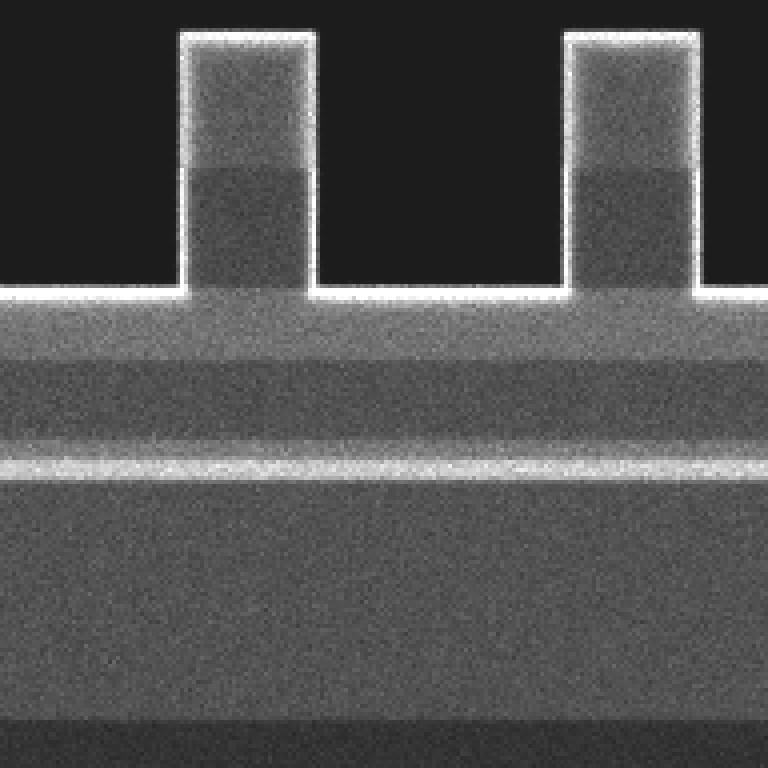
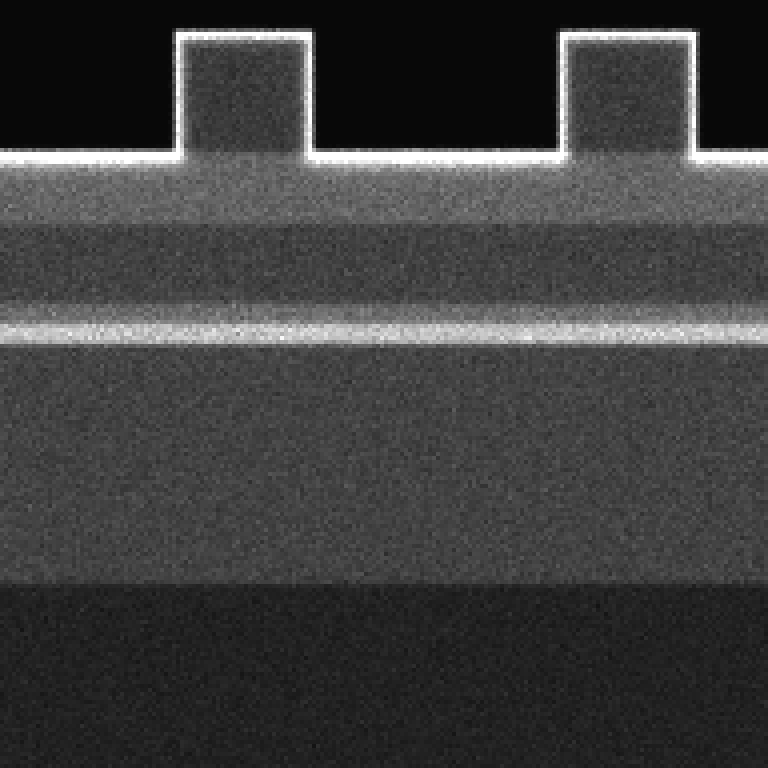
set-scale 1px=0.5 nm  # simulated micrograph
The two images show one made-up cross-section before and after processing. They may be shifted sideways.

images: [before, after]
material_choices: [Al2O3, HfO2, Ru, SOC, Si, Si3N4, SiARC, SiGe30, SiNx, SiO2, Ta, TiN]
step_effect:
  removed: SOC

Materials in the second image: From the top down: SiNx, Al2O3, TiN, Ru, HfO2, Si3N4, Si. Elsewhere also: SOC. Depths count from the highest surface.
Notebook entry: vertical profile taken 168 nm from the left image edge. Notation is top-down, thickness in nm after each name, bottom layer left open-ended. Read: empty 60, Al2O3 36, TiN 40, Ru 10, HfO2 10, Si3N4 120, Si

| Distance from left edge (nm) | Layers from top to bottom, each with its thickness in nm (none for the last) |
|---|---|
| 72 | empty 60, Al2O3 36, TiN 40, Ru 10, HfO2 10, Si3N4 120, Si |